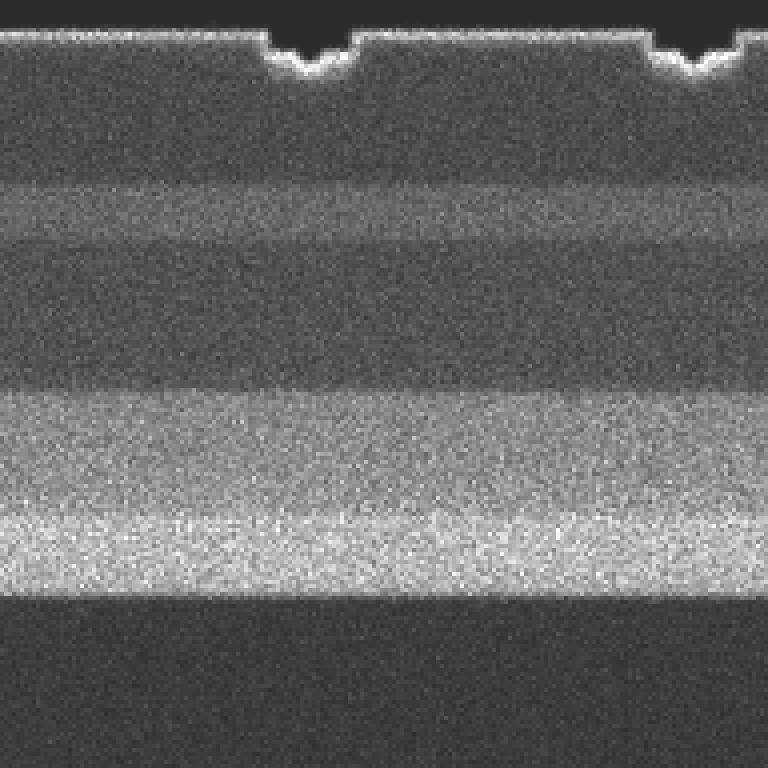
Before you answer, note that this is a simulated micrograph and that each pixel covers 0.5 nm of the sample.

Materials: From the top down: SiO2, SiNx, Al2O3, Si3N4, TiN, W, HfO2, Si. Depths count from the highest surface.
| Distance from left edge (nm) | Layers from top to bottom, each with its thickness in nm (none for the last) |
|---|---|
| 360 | empty 10, SiO2 14, SiNx 52, Al2O3 28, Si3N4 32, TiN 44, W 62, HfO2 40, Si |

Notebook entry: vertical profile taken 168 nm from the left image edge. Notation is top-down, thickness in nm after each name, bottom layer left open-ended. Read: empty 10, SiO2 14, SiNx 52, Al2O3 28, Si3N4 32, TiN 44, W 62, HfO2 40, Si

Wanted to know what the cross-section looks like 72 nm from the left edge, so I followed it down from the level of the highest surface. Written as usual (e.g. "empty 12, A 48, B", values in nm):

SiNx 76, Al2O3 28, Si3N4 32, TiN 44, W 62, HfO2 40, Si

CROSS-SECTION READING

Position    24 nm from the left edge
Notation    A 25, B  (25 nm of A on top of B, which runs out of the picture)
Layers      SiNx 76, Al2O3 28, Si3N4 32, TiN 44, W 62, HfO2 40, Si